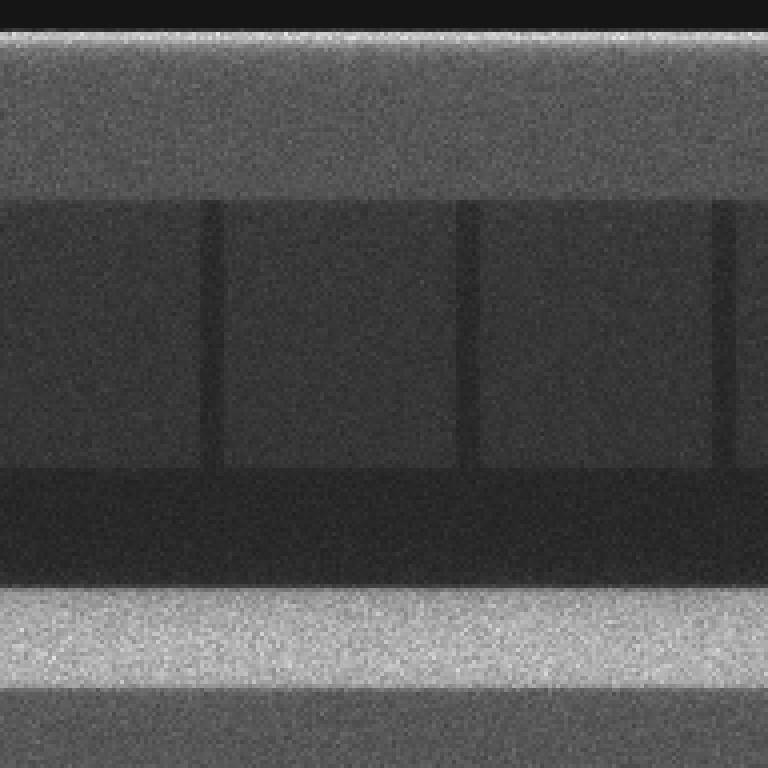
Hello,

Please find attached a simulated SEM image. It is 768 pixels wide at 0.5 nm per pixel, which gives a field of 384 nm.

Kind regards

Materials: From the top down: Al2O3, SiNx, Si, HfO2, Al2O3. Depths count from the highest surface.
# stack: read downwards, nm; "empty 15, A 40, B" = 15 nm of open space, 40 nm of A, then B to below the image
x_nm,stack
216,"Al2O3 84, SiNx 134, Si 60, HfO2 50, Al2O3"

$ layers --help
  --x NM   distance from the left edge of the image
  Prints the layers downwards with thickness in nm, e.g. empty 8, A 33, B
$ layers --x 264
Al2O3 84, SiNx 134, Si 60, HfO2 50, Al2O3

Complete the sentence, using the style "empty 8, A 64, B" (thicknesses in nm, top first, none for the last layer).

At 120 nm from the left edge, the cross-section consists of Al2O3 84, SiNx 134, Si 60, HfO2 50, Al2O3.